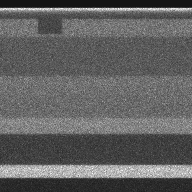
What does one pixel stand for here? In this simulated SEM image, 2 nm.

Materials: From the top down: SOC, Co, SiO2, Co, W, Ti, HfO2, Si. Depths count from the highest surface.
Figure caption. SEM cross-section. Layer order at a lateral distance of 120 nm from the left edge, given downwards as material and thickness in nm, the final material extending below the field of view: SOC 52, Co 6, SiO2 78, Co 84, W 32, Ti 62, HfO2 26, Si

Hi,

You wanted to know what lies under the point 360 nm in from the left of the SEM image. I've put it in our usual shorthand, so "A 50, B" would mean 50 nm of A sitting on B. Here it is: SOC 22, Co 36, SiO2 78, Co 84, W 32, Ti 62, HfO2 26, Si